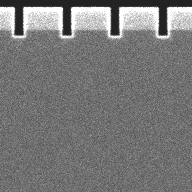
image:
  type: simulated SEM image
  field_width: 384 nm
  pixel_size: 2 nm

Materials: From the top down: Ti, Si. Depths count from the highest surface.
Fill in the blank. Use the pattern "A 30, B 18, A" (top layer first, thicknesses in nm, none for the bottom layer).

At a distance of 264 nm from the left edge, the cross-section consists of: Ti 44, Si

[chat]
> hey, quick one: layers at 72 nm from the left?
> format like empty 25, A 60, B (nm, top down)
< Ti 44, Si